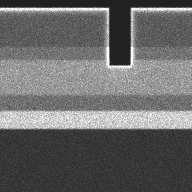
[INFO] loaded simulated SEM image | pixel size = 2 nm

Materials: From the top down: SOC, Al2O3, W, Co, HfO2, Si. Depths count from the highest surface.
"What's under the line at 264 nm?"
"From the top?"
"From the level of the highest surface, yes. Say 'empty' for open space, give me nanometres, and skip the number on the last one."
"SOC 78, Al2O3 26, W 70, Co 32, HfO2 36, Si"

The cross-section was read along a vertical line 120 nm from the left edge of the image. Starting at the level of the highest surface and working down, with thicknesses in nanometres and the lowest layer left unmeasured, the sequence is SOC 78, Al2O3 26, W 70, Co 32, HfO2 36, Si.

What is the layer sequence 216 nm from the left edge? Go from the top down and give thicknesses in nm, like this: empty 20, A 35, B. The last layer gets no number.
SOC 78, Al2O3 26, W 70, Co 32, HfO2 36, Si